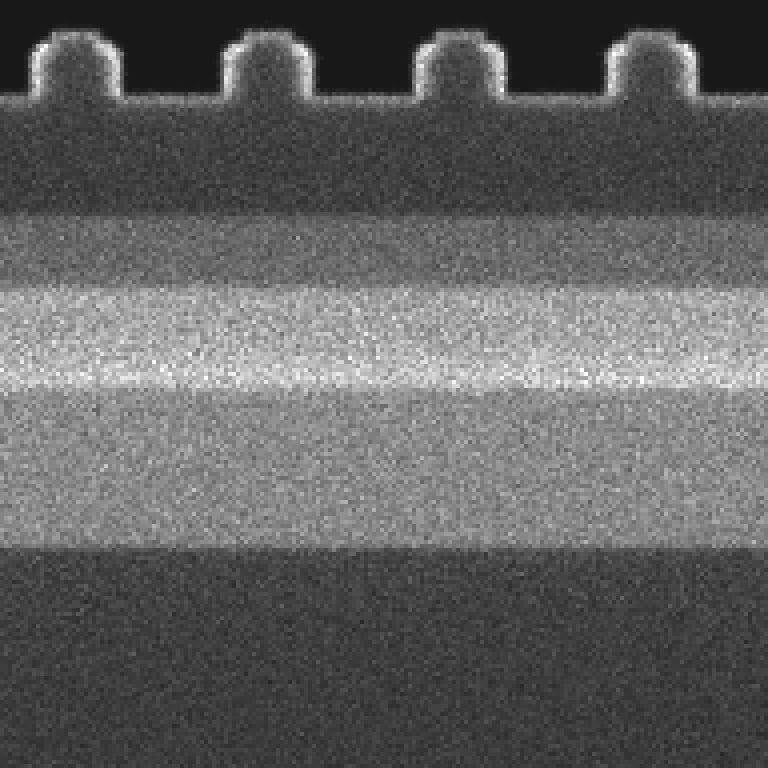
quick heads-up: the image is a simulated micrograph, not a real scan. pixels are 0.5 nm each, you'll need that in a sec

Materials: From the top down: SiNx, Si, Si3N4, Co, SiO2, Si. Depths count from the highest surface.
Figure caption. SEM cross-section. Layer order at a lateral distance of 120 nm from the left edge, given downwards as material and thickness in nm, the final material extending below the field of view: empty 6, SiNx 26, Si 60, Si3N4 36, Co 50, SiO2 80, Si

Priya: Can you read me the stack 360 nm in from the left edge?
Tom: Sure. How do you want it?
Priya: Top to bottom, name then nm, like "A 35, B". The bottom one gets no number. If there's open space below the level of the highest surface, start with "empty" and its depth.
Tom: empty 32, Si 60, Si3N4 36, Co 50, SiO2 80, Si